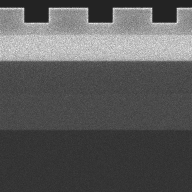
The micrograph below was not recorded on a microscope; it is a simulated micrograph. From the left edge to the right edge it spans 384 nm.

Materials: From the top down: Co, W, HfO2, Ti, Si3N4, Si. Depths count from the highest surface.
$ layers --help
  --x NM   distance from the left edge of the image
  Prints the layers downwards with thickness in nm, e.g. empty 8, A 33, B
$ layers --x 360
Co 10, W 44, HfO2 52, Ti 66, Si3N4 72, Si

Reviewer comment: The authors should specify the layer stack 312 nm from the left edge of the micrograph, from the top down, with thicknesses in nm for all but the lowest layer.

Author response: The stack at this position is empty 30, W 24, HfO2 52, Ti 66, Si3N4 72, Si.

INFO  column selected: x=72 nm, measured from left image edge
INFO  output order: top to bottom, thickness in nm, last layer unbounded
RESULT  empty 30, W 24, HfO2 52, Ti 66, Si3N4 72, Si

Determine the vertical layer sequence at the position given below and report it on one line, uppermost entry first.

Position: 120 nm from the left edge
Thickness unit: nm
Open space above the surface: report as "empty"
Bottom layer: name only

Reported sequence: Co 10, W 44, HfO2 52, Ti 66, Si3N4 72, Si